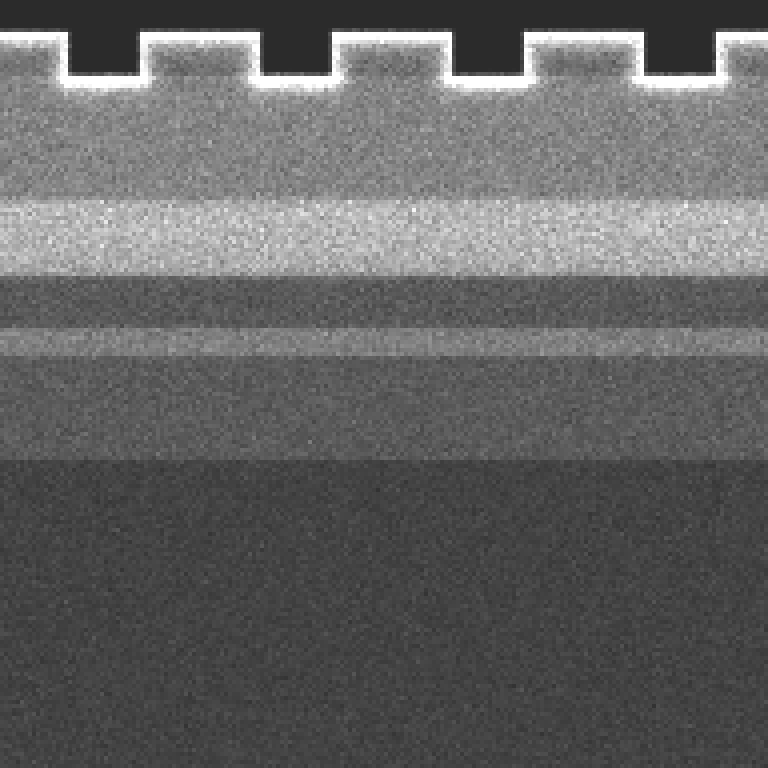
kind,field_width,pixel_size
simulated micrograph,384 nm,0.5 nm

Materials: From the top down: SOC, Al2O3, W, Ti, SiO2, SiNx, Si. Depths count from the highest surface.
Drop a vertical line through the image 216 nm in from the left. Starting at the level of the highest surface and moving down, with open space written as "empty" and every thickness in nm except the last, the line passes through SOC 22, Al2O3 62, W 38, Ti 26, SiO2 14, SiNx 52, Si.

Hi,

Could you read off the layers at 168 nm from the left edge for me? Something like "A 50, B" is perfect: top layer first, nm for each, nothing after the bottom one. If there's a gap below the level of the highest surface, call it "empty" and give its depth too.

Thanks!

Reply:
SOC 22, Al2O3 62, W 38, Ti 26, SiO2 14, SiNx 52, Si